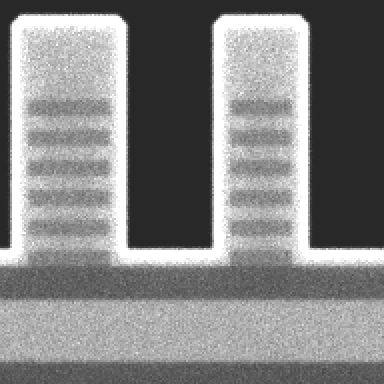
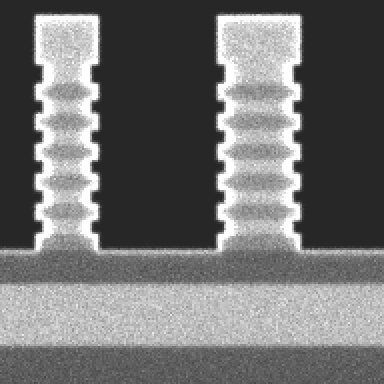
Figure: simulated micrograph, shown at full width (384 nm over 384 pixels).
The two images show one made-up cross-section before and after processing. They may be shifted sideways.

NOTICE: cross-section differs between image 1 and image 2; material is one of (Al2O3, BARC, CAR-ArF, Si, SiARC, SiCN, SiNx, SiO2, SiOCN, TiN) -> removed: Al2O3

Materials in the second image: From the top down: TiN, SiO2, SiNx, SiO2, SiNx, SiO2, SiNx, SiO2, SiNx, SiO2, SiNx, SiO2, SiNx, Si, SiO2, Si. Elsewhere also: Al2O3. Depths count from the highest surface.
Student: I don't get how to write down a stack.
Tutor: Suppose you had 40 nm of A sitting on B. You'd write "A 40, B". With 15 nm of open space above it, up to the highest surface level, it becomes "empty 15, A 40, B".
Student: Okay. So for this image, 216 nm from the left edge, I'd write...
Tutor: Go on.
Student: empty 234, Si 34, SiO2 62, Si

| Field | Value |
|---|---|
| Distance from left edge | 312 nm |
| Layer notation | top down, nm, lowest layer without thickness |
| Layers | empty 234, Si 34, SiO2 62, Si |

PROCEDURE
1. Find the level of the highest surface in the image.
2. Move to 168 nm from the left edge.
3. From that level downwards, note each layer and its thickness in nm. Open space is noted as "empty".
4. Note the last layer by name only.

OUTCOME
empty 234, Si 34, SiO2 62, Si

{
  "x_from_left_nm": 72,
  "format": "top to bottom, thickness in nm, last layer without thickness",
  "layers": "TiN 48, SiO2 20, SiNx 16, SiO2 14, SiNx 16, SiO2 14, SiNx 16, SiO2 14, SiNx 16, SiO2 14, SiNx 16, SiO2 14, SiNx 16, Si 34, SiO2 62, Si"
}